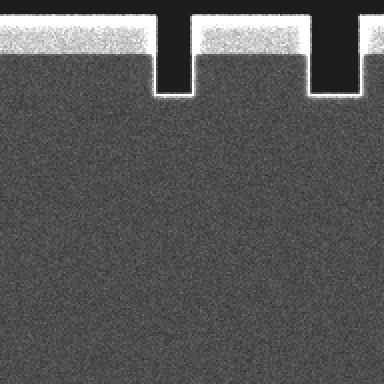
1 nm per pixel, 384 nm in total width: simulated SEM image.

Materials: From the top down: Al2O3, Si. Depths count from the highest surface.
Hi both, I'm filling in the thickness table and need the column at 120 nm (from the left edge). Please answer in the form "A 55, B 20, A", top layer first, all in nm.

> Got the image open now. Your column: Al2O3 38, Si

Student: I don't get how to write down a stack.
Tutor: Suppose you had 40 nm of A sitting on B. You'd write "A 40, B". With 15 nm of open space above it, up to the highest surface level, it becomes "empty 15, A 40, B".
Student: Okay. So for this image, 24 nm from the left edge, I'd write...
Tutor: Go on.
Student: Al2O3 38, Si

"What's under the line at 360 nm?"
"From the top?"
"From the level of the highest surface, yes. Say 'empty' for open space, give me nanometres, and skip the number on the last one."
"Al2O3 38, Si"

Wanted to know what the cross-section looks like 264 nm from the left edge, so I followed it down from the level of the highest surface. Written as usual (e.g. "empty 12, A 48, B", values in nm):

Al2O3 38, Si